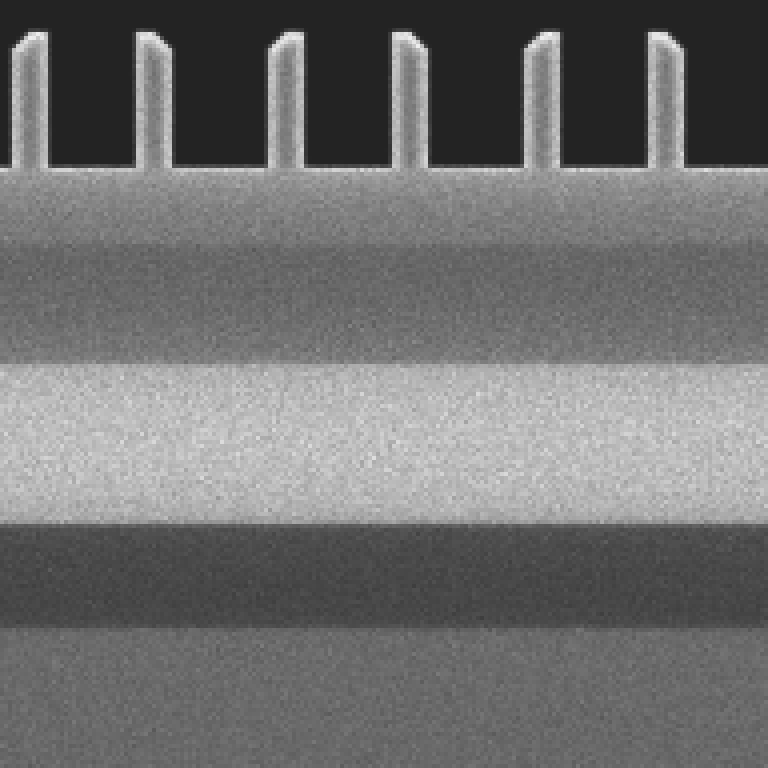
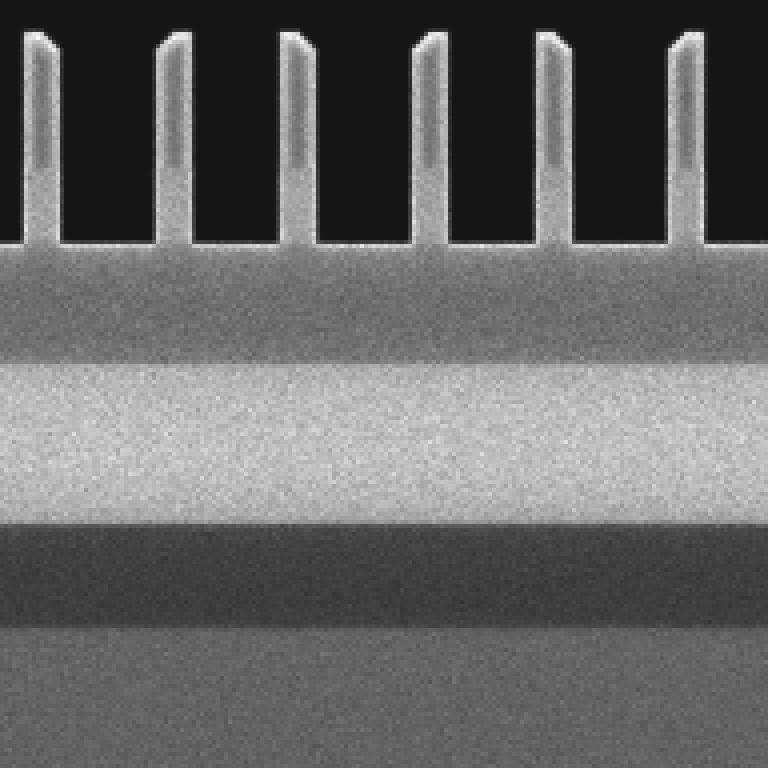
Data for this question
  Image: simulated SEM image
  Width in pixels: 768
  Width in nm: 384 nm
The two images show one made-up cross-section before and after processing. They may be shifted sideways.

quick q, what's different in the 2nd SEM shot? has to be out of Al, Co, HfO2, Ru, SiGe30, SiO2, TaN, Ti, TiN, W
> W removed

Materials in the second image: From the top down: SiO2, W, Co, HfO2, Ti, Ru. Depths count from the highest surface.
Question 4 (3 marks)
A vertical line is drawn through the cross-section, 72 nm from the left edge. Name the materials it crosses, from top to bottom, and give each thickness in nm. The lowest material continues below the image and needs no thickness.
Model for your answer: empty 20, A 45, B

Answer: empty 106, Co 60, HfO2 80, Ti 52, Ru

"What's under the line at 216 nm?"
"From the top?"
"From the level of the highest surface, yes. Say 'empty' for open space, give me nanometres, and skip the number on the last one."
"SiO2 68, W 38, Co 60, HfO2 80, Ti 52, Ru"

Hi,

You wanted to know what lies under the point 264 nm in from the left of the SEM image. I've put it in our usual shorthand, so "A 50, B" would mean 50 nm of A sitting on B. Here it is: empty 106, Co 60, HfO2 80, Ti 52, Ru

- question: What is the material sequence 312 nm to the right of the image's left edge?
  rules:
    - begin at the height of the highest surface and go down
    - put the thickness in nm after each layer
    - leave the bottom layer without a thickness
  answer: empty 106, Co 60, HfO2 80, Ti 52, Ru